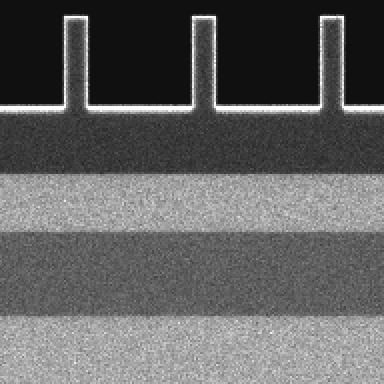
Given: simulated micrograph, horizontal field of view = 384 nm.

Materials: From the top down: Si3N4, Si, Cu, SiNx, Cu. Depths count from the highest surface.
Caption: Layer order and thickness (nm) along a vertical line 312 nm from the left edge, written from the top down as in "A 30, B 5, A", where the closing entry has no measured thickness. empty 90, Si3N4 8, Si 60, Cu 58, SiNx 84, Cu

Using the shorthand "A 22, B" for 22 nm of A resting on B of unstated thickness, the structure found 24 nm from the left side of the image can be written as empty 90, Si3N4 8, Si 60, Cu 58, SiNx 84, Cu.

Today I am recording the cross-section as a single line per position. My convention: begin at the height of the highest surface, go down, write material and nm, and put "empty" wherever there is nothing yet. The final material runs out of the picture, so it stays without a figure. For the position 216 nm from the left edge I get empty 90, Si3N4 8, Si 60, Cu 58, SiNx 84, Cu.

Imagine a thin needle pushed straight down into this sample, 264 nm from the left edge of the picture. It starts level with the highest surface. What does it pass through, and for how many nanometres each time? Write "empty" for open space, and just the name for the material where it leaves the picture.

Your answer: empty 90, Si3N4 8, Si 60, Cu 58, SiNx 84, Cu